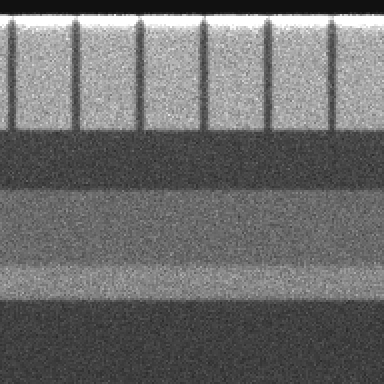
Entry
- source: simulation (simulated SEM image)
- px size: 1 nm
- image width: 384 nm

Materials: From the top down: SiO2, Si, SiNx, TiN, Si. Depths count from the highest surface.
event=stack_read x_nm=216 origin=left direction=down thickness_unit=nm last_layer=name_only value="SiO2 114, Si 60, SiNx 76, TiN 34, Si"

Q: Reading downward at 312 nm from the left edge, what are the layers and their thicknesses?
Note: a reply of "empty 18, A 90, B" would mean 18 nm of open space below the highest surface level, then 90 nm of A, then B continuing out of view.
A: SiO2 114, Si 60, SiNx 76, TiN 34, Si